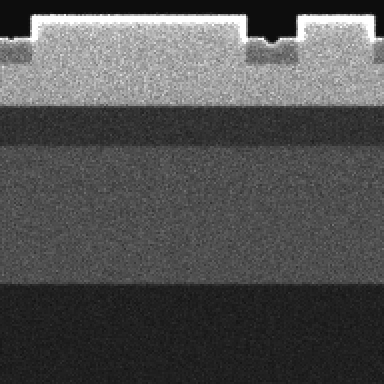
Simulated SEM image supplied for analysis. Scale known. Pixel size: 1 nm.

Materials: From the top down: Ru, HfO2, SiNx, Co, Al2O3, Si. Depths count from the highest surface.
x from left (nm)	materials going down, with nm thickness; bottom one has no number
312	HfO2 90, SiNx 40, Co 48, Al2O3 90, Si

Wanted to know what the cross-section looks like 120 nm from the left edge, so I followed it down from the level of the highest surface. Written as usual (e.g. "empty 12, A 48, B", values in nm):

HfO2 90, SiNx 40, Co 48, Al2O3 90, Si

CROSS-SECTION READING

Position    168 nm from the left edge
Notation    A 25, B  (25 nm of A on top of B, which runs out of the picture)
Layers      HfO2 90, SiNx 40, Co 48, Al2O3 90, Si